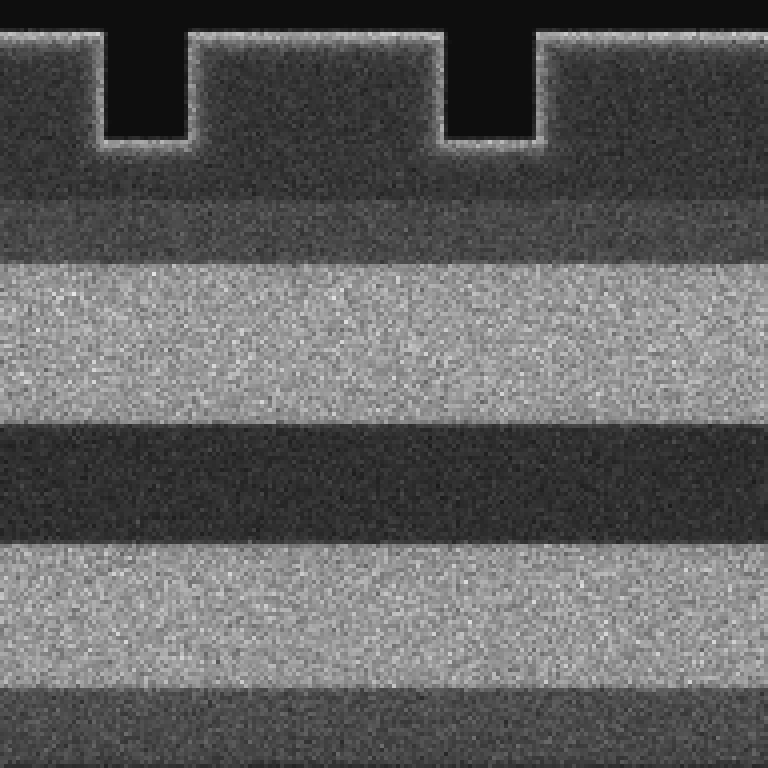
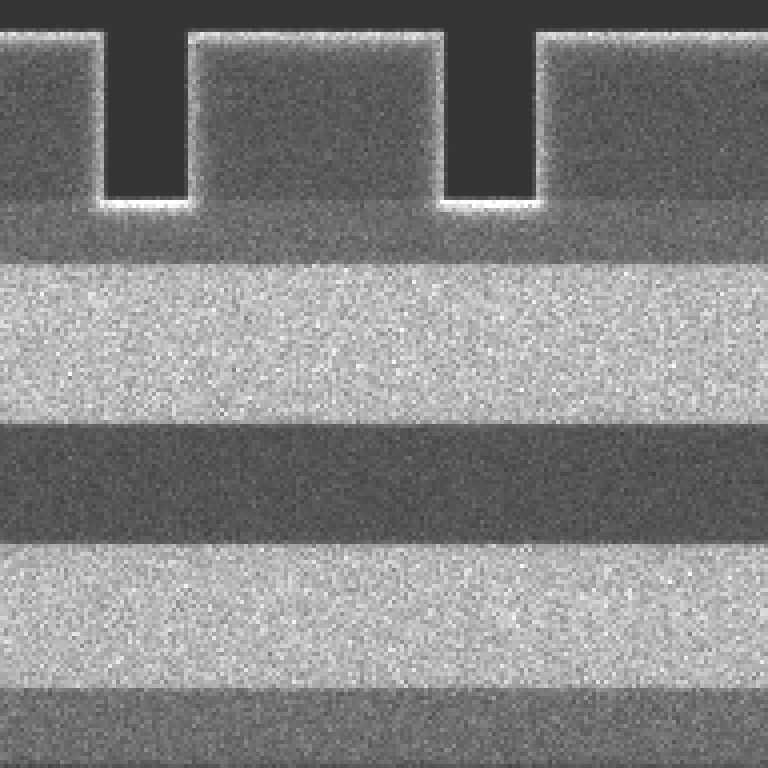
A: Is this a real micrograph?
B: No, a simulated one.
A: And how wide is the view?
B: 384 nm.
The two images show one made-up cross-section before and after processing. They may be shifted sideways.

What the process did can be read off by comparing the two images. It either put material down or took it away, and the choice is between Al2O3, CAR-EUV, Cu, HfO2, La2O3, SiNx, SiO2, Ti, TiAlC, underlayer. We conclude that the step removed underlayer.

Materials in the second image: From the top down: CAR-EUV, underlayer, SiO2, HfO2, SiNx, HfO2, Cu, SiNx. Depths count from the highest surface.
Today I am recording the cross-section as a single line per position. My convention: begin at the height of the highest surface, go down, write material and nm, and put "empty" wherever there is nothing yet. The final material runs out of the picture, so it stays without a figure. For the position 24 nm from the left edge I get CAR-EUV 54, underlayer 30, SiO2 32, HfO2 80, SiNx 60, HfO2 72, Cu 38, SiNx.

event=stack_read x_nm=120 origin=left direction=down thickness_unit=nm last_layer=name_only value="CAR-EUV 54, underlayer 30, SiO2 32, HfO2 80, SiNx 60, HfO2 72, Cu 38, SiNx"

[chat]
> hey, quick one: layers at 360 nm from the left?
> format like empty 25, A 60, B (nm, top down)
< CAR-EUV 54, underlayer 30, SiO2 32, HfO2 80, SiNx 60, HfO2 72, Cu 38, SiNx